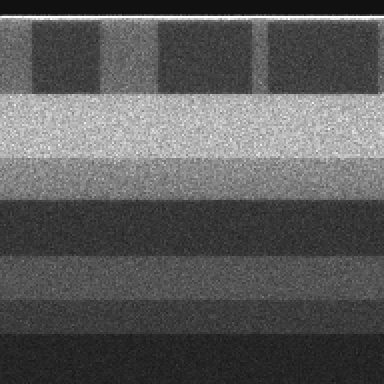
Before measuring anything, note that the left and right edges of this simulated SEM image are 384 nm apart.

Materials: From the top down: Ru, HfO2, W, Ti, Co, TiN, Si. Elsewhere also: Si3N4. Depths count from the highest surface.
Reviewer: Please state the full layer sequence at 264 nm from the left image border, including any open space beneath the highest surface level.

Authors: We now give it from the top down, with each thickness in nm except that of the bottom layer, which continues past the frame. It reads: Ru 78, HfO2 64, W 42, Ti 56, Co 44, TiN 34, Si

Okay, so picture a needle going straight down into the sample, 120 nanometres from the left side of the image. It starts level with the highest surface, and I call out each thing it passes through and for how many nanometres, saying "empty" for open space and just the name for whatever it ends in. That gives Ru 78, HfO2 64, W 42, Ti 56, Co 44, TiN 34, Si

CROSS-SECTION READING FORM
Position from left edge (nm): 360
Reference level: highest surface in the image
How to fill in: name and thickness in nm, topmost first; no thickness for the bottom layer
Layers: Si3N4 78, HfO2 64, W 42, Ti 56, Co 44, TiN 34, Si